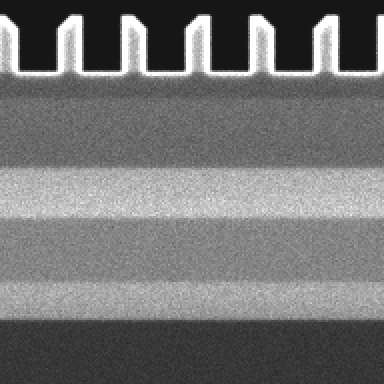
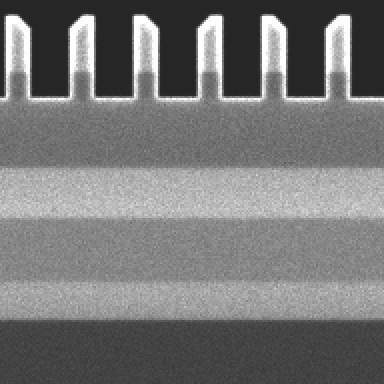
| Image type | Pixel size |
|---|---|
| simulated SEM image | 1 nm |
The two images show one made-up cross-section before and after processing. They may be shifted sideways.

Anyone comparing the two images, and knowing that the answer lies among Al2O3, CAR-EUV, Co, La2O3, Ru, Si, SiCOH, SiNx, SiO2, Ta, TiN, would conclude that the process removed SiNx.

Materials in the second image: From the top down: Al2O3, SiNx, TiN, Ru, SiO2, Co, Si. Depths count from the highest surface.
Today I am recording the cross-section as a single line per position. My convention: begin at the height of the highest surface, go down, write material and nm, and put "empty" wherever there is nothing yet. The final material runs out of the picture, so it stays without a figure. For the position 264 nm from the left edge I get Al2O3 56, SiNx 26, TiN 70, Ru 50, SiO2 64, Co 38, Si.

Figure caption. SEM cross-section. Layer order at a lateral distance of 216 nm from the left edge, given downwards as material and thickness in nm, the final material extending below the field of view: Al2O3 56, SiNx 26, TiN 70, Ru 50, SiO2 64, Co 38, Si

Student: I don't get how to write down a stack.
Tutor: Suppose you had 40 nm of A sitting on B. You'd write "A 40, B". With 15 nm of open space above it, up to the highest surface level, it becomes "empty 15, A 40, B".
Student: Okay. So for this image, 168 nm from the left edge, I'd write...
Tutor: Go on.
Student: empty 82, TiN 70, Ru 50, SiO2 64, Co 38, Si